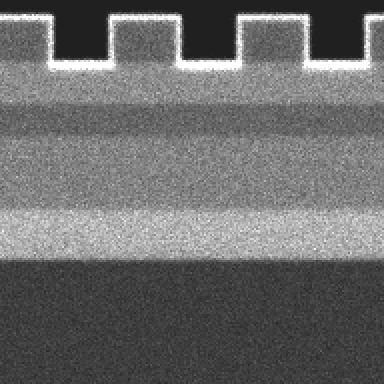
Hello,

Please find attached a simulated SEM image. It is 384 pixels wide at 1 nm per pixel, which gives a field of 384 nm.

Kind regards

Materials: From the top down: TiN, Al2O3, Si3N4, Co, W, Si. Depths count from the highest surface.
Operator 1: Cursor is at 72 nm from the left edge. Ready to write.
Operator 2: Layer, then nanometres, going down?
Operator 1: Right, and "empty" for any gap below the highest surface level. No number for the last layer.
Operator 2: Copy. empty 46, Al2O3 42, Si3N4 32, Co 74, W 50, Si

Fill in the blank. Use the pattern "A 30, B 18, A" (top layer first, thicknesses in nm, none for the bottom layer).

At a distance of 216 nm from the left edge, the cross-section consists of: empty 46, Al2O3 42, Si3N4 32, Co 74, W 50, Si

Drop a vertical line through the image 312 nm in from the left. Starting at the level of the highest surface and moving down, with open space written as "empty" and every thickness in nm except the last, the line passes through empty 46, Al2O3 42, Si3N4 32, Co 74, W 50, Si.